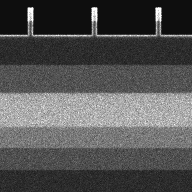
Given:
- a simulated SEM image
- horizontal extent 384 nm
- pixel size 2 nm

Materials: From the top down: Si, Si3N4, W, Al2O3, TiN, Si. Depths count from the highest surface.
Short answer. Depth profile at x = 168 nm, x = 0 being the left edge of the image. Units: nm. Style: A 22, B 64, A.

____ empty 54, Si 60, Si3N4 56, W 68, Al2O3 42, TiN 44, Si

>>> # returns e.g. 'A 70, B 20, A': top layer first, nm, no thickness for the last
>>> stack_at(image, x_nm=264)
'empty 54, Si 60, Si3N4 56, W 68, Al2O3 42, TiN 44, Si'